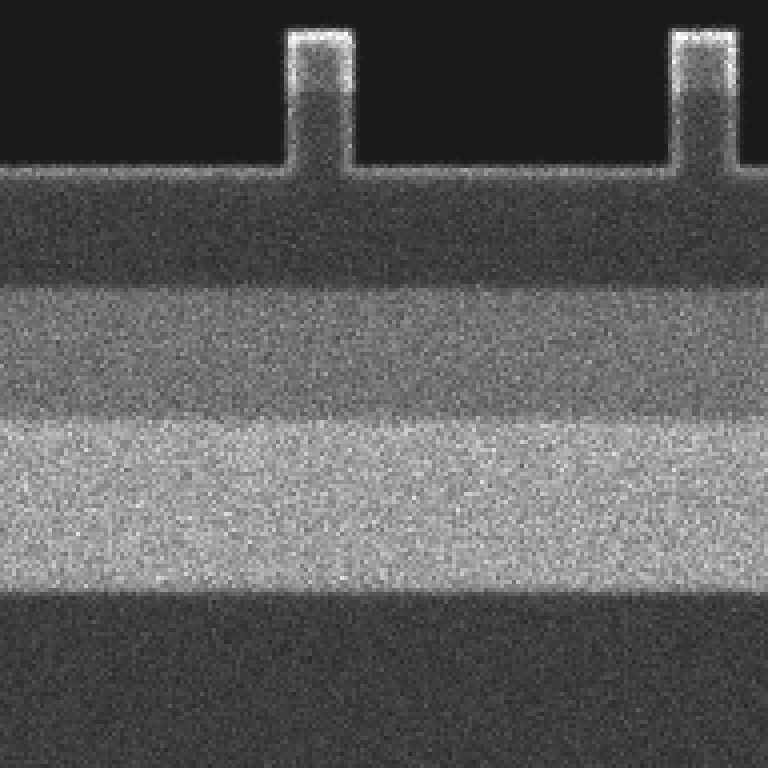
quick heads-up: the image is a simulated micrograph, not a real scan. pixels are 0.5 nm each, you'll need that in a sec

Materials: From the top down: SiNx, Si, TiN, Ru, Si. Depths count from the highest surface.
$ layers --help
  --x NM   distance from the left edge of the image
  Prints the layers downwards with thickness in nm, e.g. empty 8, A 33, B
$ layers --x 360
SiNx 30, Si 98, TiN 66, Ru 86, Si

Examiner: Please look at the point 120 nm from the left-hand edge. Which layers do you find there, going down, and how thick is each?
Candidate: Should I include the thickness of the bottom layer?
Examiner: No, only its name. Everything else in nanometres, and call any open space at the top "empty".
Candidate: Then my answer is empty 68, Si 60, TiN 66, Ru 86, Si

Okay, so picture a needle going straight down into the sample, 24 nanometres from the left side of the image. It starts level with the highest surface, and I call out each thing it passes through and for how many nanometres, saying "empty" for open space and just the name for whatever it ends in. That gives empty 68, Si 60, TiN 66, Ru 86, Si